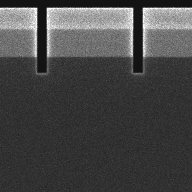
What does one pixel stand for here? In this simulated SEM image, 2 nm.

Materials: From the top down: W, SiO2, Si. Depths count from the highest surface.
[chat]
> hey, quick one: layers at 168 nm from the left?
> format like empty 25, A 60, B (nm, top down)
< W 42, SiO2 56, Si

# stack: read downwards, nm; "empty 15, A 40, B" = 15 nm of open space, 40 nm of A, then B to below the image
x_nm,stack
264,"W 42, SiO2 56, Si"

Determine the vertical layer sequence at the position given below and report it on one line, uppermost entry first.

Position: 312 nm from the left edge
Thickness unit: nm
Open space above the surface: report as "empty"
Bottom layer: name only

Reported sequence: W 42, SiO2 56, Si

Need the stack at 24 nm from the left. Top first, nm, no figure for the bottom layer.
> W 42, SiO2 56, Si